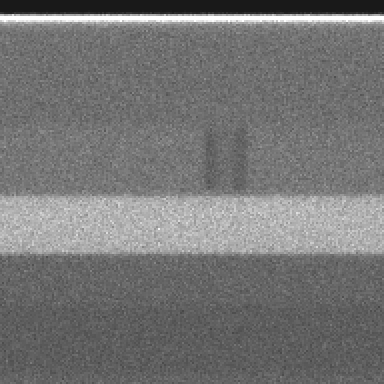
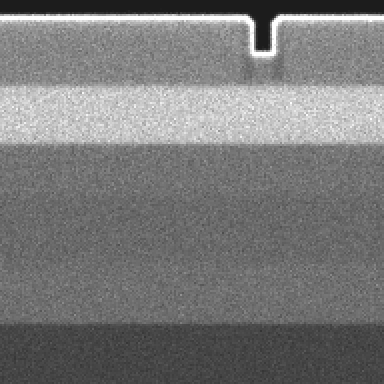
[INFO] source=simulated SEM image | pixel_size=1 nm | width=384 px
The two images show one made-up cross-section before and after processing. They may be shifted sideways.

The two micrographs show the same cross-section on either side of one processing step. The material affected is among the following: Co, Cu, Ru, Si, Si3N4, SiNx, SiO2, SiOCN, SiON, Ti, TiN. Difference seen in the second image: Si3N4 removed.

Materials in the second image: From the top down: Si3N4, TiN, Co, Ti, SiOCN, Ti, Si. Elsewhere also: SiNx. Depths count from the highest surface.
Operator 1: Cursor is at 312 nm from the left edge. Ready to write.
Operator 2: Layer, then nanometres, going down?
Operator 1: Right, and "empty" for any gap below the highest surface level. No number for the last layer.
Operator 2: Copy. TiN 70, Co 58, Ti 52, SiOCN 68, Ti 60, Si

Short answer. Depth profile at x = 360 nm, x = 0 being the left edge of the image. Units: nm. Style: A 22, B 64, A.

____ TiN 70, Co 58, Ti 52, SiOCN 68, Ti 60, Si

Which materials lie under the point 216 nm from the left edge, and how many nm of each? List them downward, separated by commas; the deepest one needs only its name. TiN 70, Co 58, Ti 52, SiOCN 68, Ti 60, Si